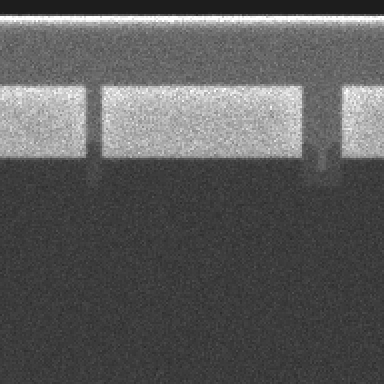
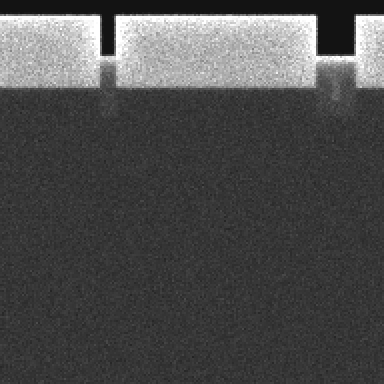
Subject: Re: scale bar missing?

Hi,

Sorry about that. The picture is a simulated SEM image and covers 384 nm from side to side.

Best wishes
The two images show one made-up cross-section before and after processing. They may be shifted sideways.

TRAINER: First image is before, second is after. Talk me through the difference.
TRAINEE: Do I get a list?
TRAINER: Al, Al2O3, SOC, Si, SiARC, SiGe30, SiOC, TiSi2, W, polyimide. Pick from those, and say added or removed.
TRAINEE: removed: SOC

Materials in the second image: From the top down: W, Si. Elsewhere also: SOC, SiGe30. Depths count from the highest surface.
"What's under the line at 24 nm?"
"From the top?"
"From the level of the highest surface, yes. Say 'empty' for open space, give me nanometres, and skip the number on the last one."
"W 72, Si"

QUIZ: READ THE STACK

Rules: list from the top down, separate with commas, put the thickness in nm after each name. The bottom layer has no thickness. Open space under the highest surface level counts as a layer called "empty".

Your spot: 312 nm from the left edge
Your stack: W 72, Si